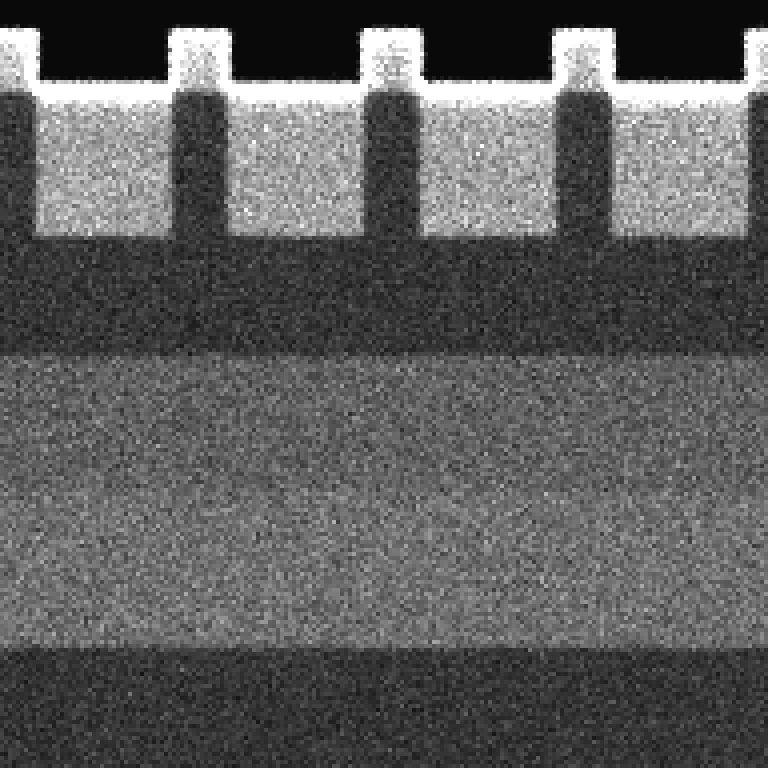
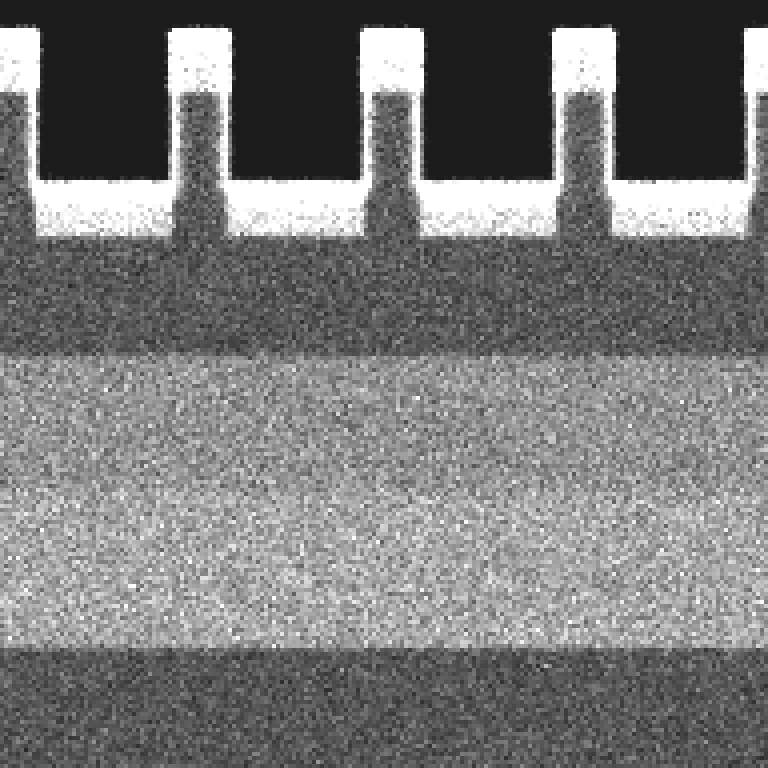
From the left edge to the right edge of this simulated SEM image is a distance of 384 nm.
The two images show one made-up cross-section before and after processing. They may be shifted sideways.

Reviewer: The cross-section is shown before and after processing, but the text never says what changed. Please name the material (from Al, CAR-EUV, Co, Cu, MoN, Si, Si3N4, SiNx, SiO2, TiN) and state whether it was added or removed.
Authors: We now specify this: SiO2, removed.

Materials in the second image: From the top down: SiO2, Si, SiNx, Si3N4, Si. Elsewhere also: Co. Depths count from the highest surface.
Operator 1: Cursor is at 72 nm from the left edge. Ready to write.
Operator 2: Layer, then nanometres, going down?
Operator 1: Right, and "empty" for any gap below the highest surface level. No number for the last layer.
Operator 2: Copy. empty 76, SiO2 26, Si 60, SiNx 68, Si3N4 78, Si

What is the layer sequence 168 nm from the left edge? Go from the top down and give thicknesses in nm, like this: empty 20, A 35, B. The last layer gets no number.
empty 76, SiO2 26, Si 60, SiNx 68, Si3N4 78, Si